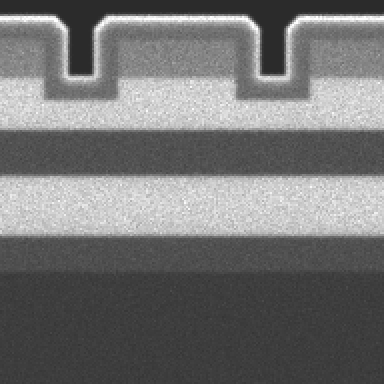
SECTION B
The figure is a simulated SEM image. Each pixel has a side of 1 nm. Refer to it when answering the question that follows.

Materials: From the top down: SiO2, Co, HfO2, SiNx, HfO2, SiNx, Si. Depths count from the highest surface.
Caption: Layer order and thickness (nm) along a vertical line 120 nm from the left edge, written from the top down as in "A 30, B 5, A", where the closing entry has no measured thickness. SiO2 24, Co 38, HfO2 52, SiNx 46, HfO2 60, SiNx 36, Si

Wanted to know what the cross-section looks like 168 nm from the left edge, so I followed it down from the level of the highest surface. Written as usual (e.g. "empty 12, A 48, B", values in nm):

SiO2 24, Co 38, HfO2 52, SiNx 46, HfO2 60, SiNx 36, Si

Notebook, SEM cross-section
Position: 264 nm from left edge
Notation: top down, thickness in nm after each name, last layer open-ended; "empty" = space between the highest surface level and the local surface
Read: empty 60, SiO2 24, HfO2 30, SiNx 46, HfO2 60, SiNx 36, Si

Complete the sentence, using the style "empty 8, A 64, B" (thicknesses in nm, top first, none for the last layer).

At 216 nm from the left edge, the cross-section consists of SiO2 24, Co 38, HfO2 52, SiNx 46, HfO2 60, SiNx 36, Si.